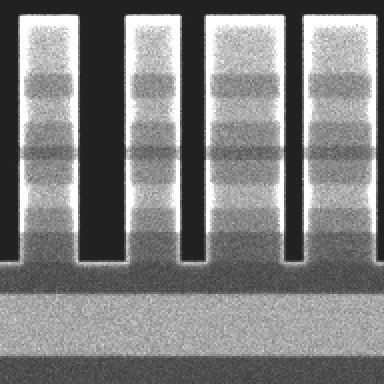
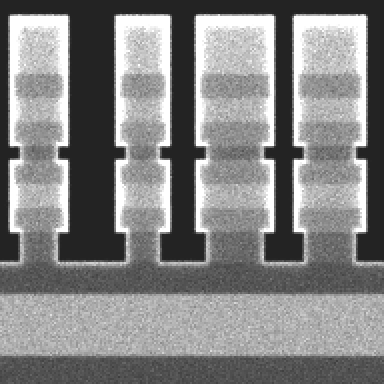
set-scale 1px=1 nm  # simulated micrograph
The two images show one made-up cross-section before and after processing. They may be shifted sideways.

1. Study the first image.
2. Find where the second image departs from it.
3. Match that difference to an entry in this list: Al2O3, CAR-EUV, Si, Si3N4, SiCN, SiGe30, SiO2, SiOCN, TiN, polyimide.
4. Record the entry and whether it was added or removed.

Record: SiGe30 / removed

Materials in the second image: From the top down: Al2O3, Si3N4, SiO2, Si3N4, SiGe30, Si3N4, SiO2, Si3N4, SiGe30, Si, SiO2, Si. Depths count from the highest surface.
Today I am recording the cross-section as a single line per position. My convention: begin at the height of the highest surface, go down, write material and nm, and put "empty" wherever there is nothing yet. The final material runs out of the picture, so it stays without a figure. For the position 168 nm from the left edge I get Al2O3 58, Si3N4 24, SiO2 24, Si3N4 24, empty 14, Si3N4 24, SiO2 24, Si3N4 24, empty 30, Si 32, SiO2 62, Si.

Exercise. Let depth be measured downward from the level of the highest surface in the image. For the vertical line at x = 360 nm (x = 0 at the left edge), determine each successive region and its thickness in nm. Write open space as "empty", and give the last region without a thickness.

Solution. Al2O3 58, Si3N4 24, SiO2 24, Si3N4 24, empty 14, Si3N4 24, SiO2 24, Si3N4 24, empty 30, Si 32, SiO2 62, Si